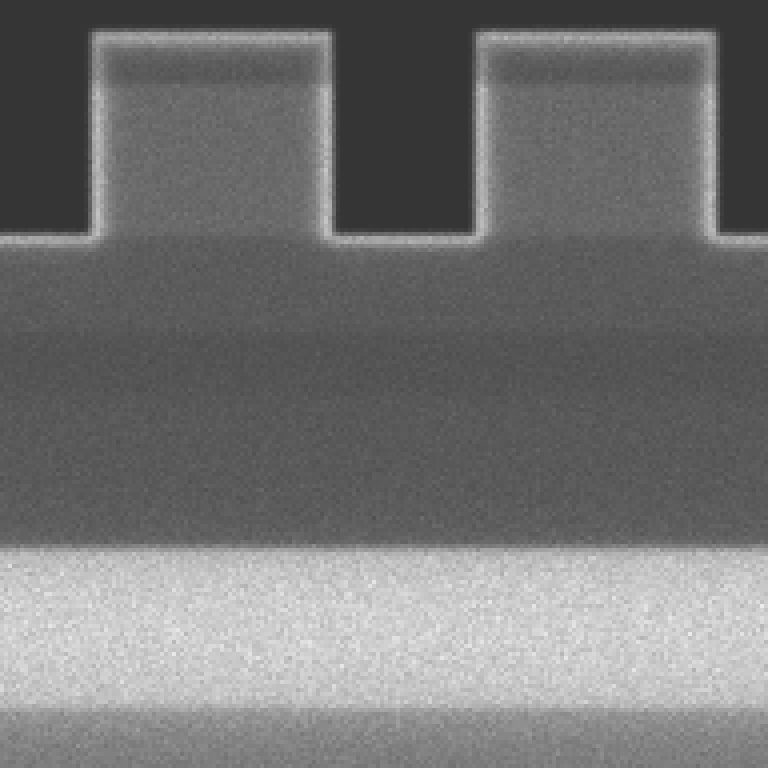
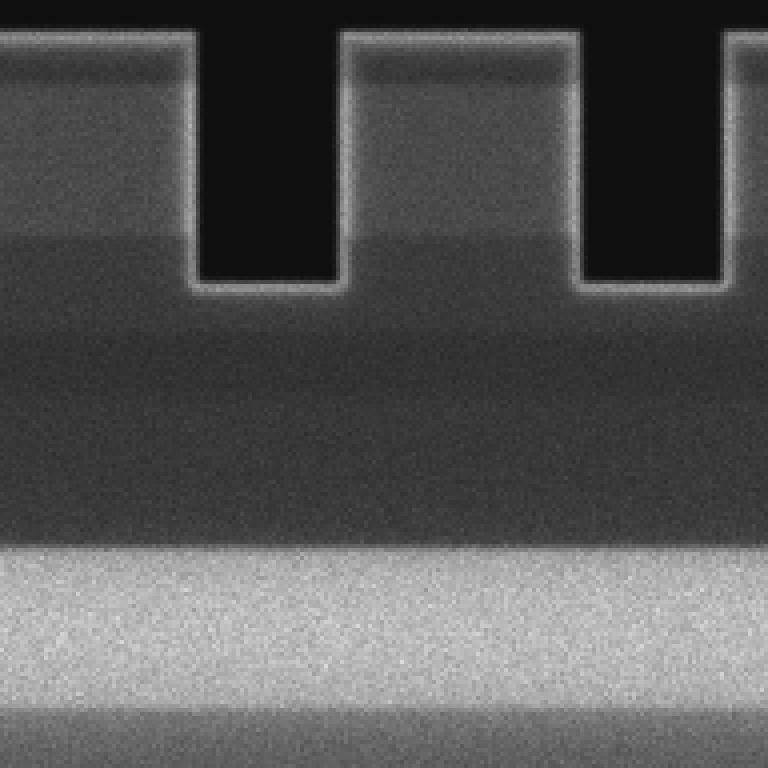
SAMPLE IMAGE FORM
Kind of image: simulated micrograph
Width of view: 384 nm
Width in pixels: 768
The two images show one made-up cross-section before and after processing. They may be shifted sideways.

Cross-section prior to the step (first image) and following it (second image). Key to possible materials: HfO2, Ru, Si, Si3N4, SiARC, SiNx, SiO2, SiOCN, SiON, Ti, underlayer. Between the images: Si3N4 was removed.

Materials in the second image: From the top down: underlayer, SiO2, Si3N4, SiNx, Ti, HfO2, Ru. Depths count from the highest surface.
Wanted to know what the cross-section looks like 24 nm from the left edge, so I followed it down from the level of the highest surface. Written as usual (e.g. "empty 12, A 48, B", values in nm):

underlayer 26, SiO2 76, Si3N4 48, SiNx 32, Ti 76, HfO2 80, Ru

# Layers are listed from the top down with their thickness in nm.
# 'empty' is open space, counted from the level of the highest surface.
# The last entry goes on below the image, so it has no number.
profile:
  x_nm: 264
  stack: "underlayer 26, SiO2 76, Si3N4 48, SiNx 32, Ti 76, HfO2 80, Ru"